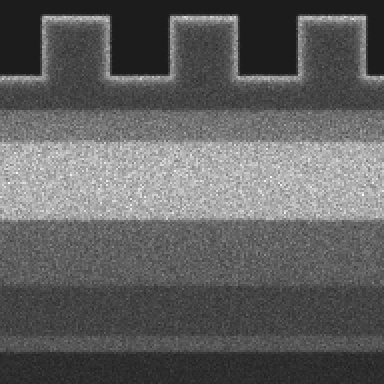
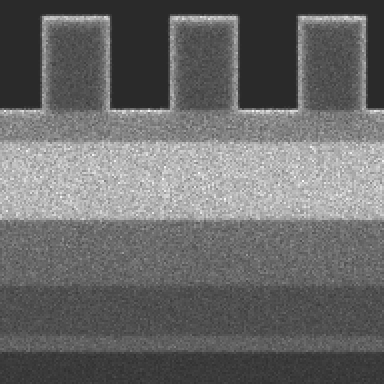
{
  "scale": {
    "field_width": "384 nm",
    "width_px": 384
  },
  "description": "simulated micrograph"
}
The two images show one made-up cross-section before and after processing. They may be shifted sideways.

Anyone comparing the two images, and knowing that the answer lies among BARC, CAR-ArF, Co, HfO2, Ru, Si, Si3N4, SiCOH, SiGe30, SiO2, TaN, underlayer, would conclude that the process removed underlayer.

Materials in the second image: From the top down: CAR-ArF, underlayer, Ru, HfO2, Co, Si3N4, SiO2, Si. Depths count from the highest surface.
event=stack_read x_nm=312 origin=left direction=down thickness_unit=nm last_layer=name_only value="CAR-ArF 60, underlayer 34, Ru 32, HfO2 78, Co 66, Si3N4 50, SiO2 16, Si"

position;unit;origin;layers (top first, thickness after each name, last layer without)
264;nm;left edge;empty 94, Ru 32, HfO2 78, Co 66, Si3N4 50, SiO2 16, Si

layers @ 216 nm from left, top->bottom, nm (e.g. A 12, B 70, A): CAR-ArF 60, underlayer 34, Ru 32, HfO2 78, Co 66, Si3N4 50, SiO2 16, Si